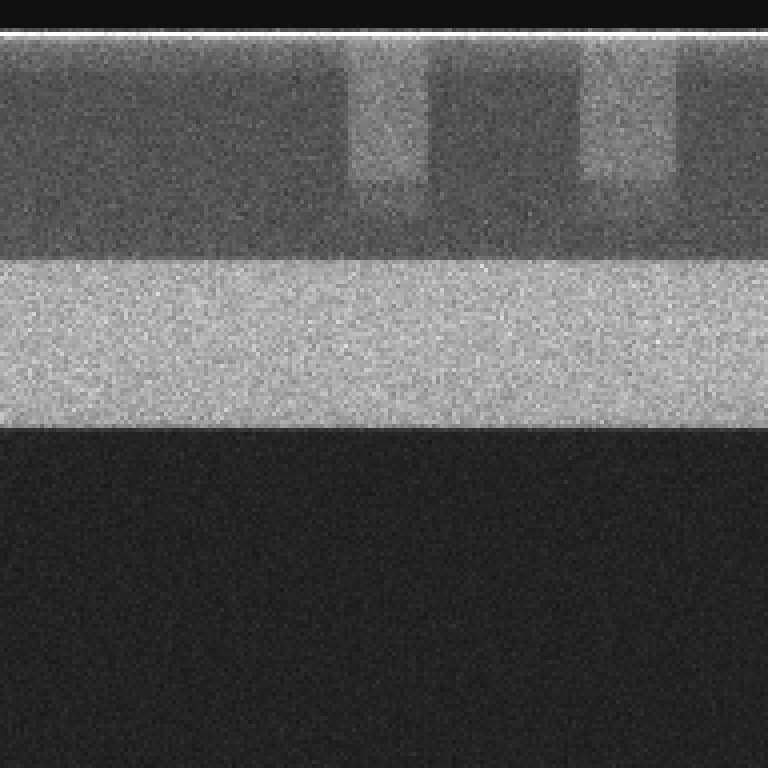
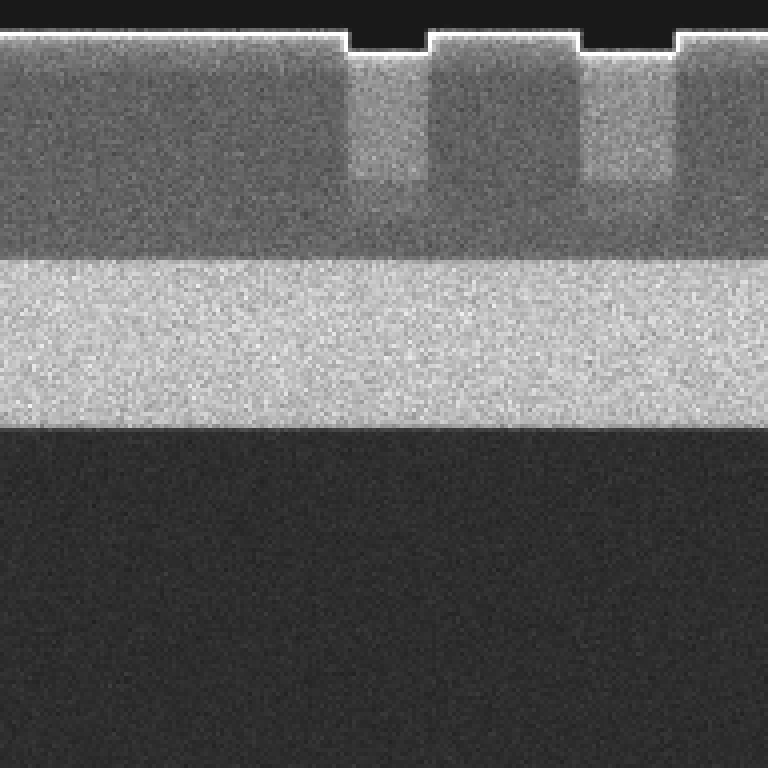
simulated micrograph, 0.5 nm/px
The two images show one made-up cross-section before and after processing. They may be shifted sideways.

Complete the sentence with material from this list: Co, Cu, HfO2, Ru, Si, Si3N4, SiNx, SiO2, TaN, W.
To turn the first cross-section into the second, W must be removed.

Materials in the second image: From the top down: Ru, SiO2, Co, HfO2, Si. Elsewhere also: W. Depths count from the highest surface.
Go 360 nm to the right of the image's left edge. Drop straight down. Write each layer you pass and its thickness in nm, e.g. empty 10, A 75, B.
Ru 20, SiO2 62, Co 32, HfO2 84, Si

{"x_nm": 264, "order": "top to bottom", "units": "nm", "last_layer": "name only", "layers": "Ru 20, SiO2 62, Co 32, HfO2 84, Si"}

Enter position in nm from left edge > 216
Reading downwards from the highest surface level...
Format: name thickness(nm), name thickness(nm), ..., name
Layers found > Ru 20, SiO2 62, Co 32, HfO2 84, Si